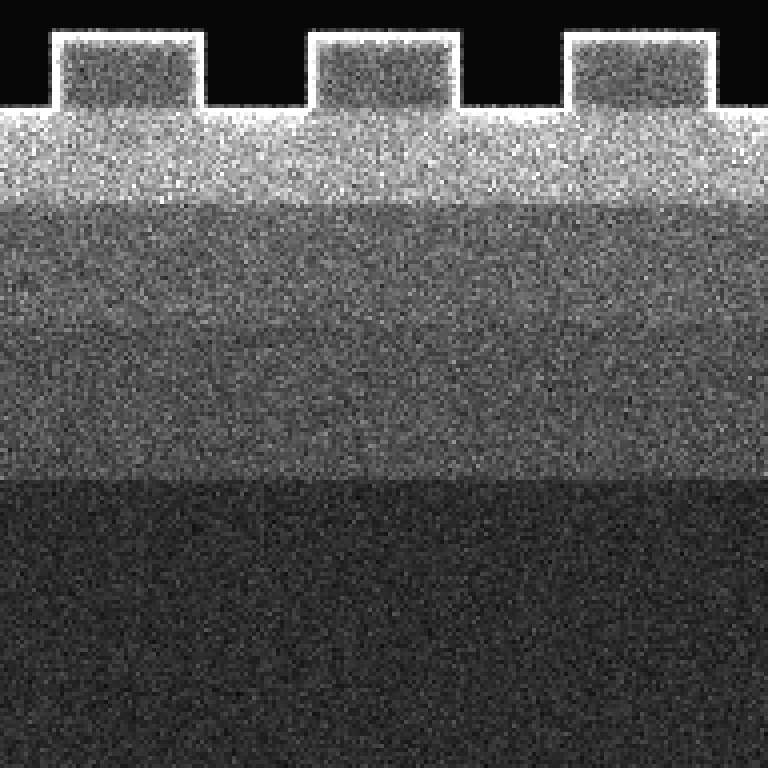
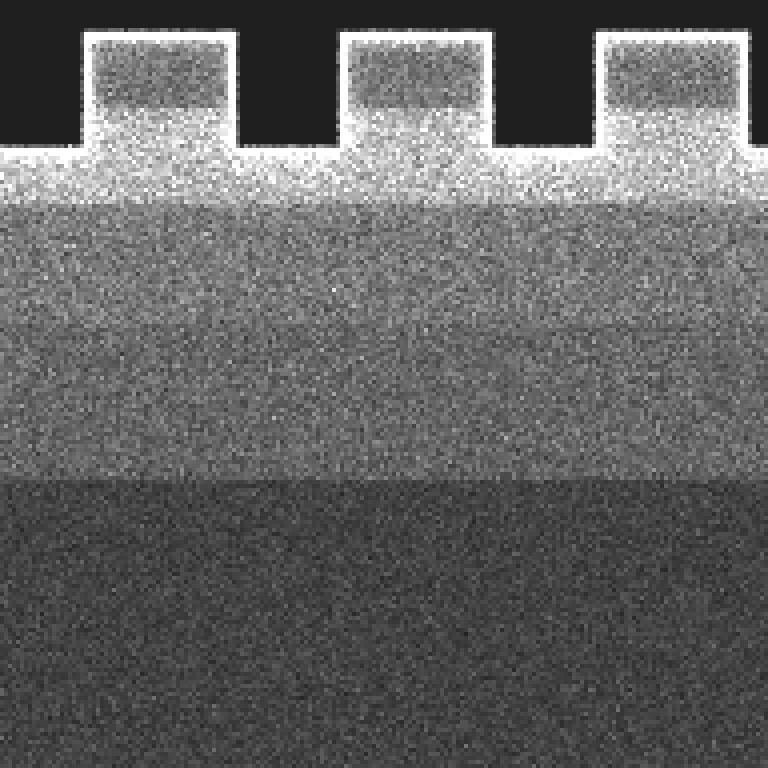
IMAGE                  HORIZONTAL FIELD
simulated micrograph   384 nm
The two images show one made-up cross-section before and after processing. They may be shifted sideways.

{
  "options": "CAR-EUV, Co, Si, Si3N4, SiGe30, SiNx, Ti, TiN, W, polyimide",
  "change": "removed",
  "material": "Co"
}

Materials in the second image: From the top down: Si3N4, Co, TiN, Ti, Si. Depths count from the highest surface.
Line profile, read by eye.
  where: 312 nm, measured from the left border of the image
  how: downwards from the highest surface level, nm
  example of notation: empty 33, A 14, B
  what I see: Si3N4 38, Co 48, TiN 60, Ti 78, Si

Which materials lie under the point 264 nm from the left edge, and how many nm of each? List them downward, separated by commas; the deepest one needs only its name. empty 58, Co 28, TiN 60, Ti 78, Si